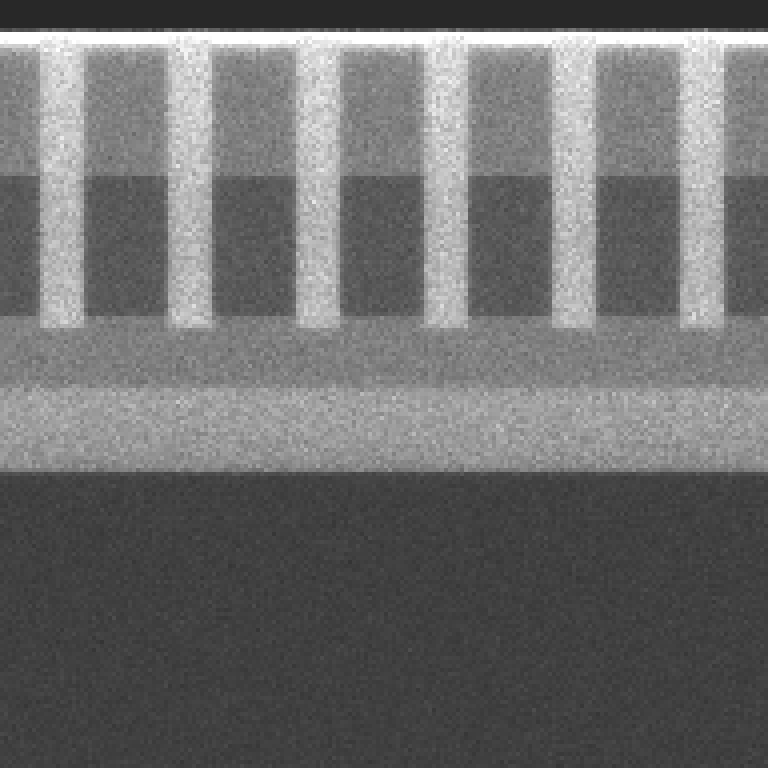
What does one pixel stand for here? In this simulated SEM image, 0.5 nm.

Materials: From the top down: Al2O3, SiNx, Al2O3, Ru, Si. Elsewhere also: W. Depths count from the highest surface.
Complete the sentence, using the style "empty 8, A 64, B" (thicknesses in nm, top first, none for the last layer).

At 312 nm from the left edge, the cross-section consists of Al2O3 72, SiNx 70, Al2O3 36, Ru 42, Si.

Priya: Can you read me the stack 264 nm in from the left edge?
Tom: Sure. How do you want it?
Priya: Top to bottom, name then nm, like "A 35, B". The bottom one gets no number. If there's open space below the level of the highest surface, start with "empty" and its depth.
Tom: Al2O3 72, SiNx 70, Al2O3 36, Ru 42, Si